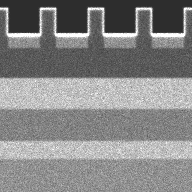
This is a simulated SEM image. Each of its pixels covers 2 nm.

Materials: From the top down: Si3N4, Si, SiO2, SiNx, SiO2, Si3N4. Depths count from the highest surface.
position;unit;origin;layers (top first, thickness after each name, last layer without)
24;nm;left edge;empty 52, Si3N4 28, Si 60, SiO2 62, SiNx 64, SiO2 36, Si3N4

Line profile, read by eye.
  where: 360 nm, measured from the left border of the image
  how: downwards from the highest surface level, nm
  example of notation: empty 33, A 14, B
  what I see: empty 52, Si3N4 28, Si 60, SiO2 62, SiNx 64, SiO2 36, Si3N4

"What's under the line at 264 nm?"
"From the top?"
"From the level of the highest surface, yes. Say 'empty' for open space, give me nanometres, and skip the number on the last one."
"empty 52, Si3N4 28, Si 60, SiO2 62, SiNx 64, SiO2 36, Si3N4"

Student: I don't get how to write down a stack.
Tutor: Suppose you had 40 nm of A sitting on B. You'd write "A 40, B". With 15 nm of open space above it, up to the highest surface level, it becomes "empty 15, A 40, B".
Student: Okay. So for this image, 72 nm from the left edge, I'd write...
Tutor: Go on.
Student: empty 52, Si3N4 28, Si 60, SiO2 62, SiNx 64, SiO2 36, Si3N4